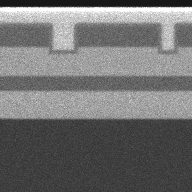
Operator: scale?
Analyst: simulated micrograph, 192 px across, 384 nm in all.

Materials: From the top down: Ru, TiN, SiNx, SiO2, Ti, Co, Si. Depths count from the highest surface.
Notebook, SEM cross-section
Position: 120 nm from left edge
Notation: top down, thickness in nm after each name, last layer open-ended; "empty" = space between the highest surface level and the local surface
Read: Ru 84, TiN 8, SiO2 44, Ti 30, Co 56, Si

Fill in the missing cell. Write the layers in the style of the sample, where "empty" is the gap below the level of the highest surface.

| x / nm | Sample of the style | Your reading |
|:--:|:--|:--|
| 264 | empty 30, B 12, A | Ru 30, TiN 8, SiNx 40, SiO2 58, Ti 30, Co 56, Si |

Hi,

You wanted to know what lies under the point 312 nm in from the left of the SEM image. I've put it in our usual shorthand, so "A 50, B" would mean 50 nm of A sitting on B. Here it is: Ru 30, TiN 8, SiNx 40, SiO2 58, Ti 30, Co 56, Si